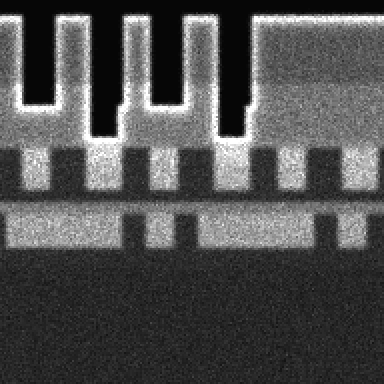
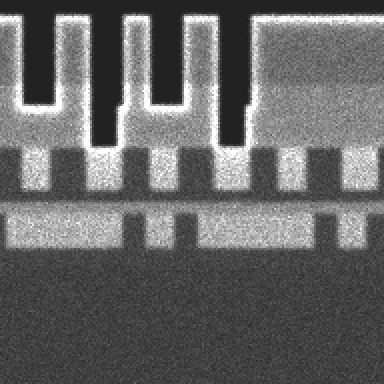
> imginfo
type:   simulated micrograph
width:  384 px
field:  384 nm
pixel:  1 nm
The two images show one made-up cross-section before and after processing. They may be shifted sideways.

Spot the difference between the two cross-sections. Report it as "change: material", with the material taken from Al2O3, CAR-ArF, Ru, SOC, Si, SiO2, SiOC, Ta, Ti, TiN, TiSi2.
removed: Al2O3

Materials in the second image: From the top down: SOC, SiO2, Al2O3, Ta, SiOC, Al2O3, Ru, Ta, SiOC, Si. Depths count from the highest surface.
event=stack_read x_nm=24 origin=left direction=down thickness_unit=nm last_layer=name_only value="empty 90, SiO2 32, Al2O3 10, Ta 42, SiOC 12, Al2O3 12, Ru 26, Ta 8, SiOC 20, Si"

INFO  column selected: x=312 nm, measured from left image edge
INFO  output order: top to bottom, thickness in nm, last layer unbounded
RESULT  SOC 68, SiO2 54, Al2O3 10, SiOC 54, Al2O3 12, Ta 34, SiOC 20, Si